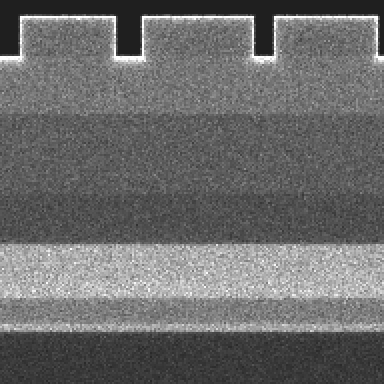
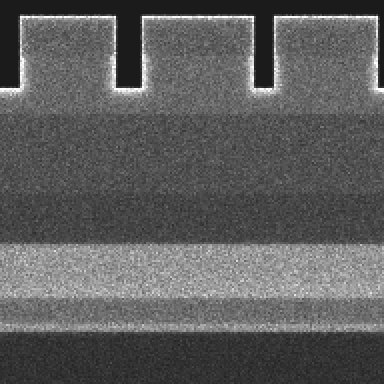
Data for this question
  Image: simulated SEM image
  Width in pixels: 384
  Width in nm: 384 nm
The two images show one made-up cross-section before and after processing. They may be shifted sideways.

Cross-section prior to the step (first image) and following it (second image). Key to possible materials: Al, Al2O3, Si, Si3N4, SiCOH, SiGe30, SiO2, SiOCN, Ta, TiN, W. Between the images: SiO2 was removed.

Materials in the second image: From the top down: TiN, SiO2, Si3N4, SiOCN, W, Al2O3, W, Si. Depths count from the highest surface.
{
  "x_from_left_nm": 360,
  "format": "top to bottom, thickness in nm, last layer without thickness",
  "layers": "TiN 40, SiO2 58, Si3N4 80, SiOCN 50, W 54, Al2O3 26, W 8, Si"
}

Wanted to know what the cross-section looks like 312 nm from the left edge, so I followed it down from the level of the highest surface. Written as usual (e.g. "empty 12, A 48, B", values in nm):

TiN 40, SiO2 58, Si3N4 80, SiOCN 50, W 54, Al2O3 26, W 8, Si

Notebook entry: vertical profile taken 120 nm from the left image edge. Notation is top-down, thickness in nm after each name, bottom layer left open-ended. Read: empty 72, SiO2 26, Si3N4 80, SiOCN 50, W 54, Al2O3 26, W 8, Si